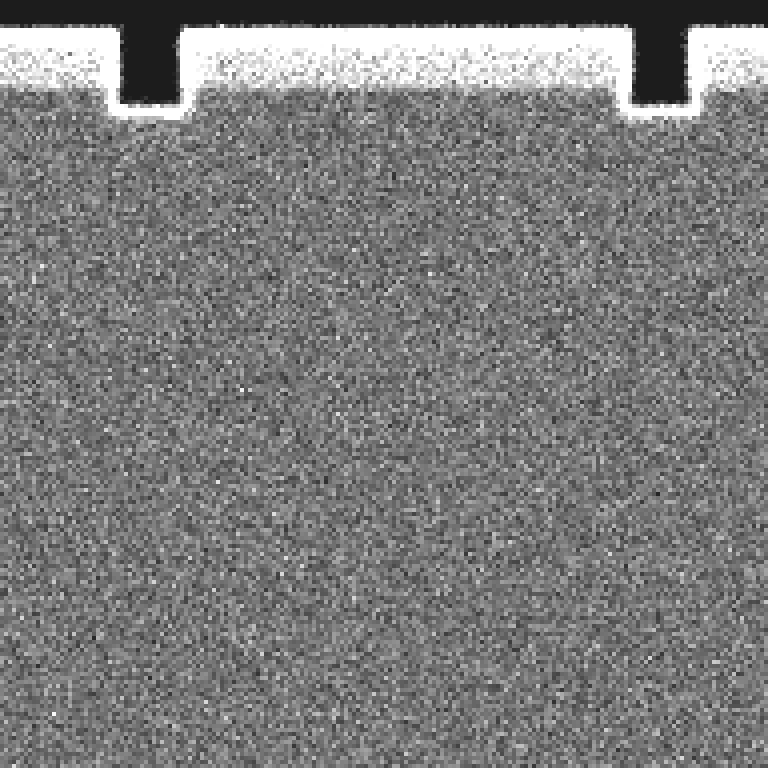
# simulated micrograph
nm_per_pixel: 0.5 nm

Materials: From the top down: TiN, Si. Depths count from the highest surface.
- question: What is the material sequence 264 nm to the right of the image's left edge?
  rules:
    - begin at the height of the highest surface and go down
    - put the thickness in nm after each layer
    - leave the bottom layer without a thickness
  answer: TiN 28, Si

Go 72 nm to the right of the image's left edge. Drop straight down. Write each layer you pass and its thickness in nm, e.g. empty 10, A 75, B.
empty 38, Si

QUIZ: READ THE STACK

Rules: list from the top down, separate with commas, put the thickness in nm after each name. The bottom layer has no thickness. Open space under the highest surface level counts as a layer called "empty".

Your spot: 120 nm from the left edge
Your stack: TiN 28, Si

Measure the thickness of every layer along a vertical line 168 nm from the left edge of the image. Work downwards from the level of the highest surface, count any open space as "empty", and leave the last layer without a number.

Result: TiN 28, Si